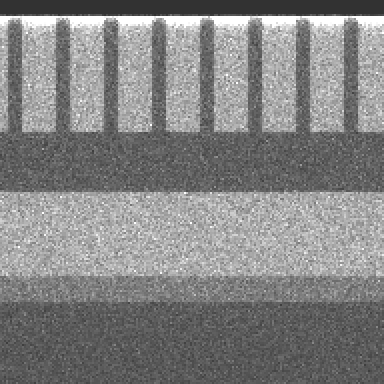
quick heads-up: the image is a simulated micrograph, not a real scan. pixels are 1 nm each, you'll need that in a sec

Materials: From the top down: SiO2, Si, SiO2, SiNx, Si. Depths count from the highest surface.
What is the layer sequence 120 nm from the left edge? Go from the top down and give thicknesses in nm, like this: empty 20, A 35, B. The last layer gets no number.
SiO2 116, Si 60, SiO2 84, SiNx 26, Si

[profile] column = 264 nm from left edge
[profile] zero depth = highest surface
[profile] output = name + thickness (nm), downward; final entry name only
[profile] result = SiO2 116, Si 60, SiO2 84, SiNx 26, Si